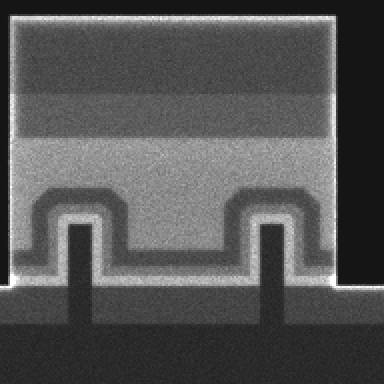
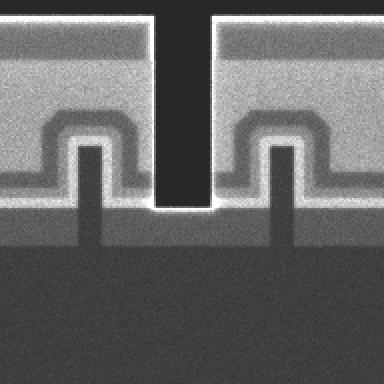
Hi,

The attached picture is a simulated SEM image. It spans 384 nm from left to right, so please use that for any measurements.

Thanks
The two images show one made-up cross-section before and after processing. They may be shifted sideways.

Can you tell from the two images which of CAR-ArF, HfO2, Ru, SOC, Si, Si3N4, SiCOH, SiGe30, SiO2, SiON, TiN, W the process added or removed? Yes, it removed SOC.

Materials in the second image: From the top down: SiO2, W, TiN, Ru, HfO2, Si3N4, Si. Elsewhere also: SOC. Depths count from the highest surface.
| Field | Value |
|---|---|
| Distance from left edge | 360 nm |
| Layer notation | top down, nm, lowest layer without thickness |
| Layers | SiO2 44, W 112, TiN 16, Ru 10, HfO2 10, Si3N4 38, Si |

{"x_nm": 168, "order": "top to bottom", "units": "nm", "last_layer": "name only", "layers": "empty 192, Si3N4 38, Si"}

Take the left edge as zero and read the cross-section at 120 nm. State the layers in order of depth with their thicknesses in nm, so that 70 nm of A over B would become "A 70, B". SiO2 44, W 50, TiN 24, Ru 64, HfO2 10, Si3N4 38, Si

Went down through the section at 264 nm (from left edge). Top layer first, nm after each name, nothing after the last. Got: SiO2 44, W 50, TiN 16, Ru 10, HfO2 72, Si3N4 38, Si